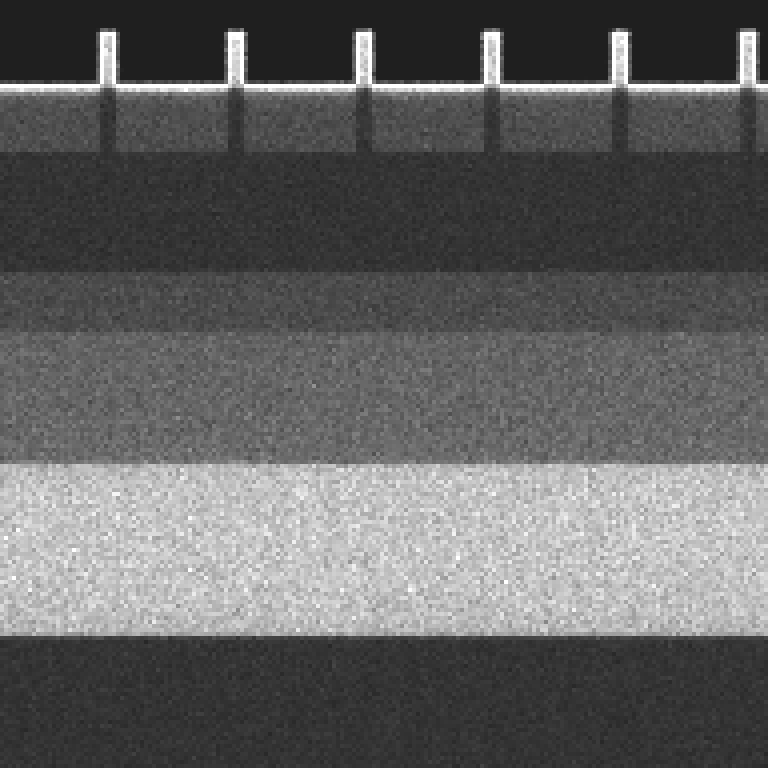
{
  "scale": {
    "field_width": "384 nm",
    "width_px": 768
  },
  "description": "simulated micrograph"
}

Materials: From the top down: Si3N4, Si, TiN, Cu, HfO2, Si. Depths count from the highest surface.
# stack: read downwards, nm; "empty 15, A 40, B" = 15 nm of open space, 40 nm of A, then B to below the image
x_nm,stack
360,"empty 26, Si3N4 34, Si 60, TiN 30, Cu 66, HfO2 86, Si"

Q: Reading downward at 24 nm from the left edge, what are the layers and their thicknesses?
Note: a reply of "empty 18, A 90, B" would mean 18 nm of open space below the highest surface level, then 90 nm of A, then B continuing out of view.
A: empty 26, Si3N4 34, Si 60, TiN 30, Cu 66, HfO2 86, Si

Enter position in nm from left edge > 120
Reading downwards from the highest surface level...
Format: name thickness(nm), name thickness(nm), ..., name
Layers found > Si3N4 28, Si 92, TiN 30, Cu 66, HfO2 86, Si